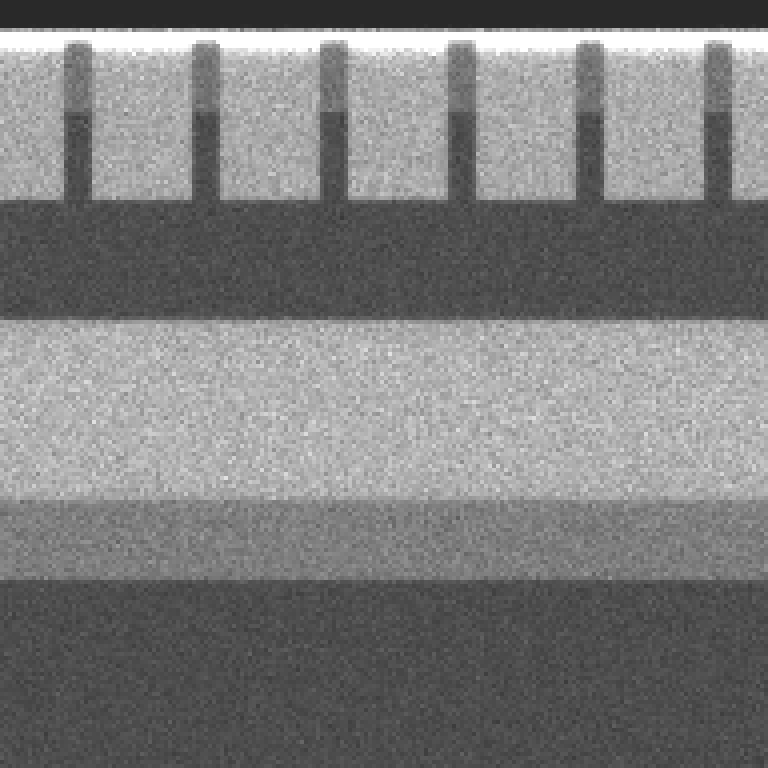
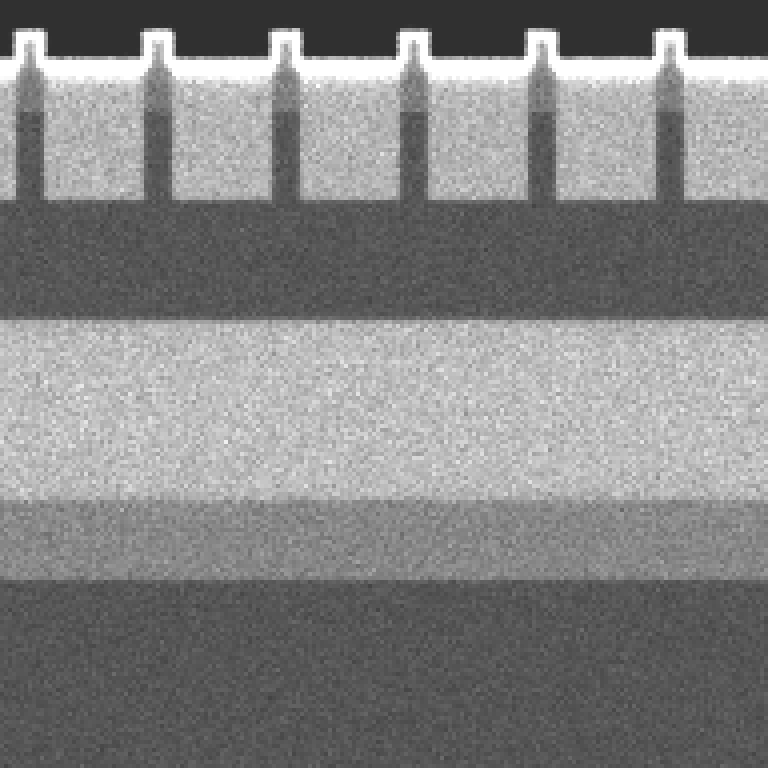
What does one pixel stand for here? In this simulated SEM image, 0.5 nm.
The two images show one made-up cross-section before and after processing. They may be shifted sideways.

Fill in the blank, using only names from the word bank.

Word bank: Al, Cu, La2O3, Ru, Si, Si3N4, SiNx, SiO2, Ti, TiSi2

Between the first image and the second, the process removed SiO2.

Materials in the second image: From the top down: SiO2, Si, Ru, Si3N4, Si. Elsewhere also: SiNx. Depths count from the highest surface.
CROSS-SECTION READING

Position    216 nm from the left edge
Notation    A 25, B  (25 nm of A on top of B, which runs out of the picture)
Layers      empty 14, SiO2 70, Si 60, Ru 90, Si3N4 40, Si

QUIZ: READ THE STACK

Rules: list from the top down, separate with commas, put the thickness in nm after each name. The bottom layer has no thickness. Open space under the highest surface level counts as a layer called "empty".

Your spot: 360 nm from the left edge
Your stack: empty 14, SiO2 70, Si 60, Ru 90, Si3N4 40, Si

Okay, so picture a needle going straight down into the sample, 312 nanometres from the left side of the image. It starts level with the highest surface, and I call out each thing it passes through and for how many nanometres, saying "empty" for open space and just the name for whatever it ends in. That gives empty 14, SiO2 70, Si 60, Ru 90, Si3N4 40, Si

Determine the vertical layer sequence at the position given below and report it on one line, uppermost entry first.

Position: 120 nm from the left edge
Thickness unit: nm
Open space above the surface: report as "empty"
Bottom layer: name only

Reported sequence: empty 14, SiO2 70, Si 60, Ru 90, Si3N4 40, Si